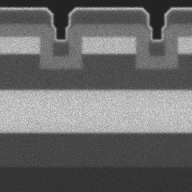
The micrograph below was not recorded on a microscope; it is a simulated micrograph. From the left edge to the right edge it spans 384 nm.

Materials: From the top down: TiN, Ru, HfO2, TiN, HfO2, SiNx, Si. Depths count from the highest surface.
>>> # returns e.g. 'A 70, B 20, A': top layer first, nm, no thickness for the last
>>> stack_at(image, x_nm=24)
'TiN 32, Ru 26, HfO2 34, TiN 72, HfO2 86, SiNx 68, Si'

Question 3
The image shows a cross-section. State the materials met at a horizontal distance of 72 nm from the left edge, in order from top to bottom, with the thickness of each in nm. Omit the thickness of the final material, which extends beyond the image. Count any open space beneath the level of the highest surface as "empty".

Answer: TiN 32, Ru 26, HfO2 34, TiN 72, HfO2 86, SiNx 68, Si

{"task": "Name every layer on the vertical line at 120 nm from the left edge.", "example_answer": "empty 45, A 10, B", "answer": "empty 64, TiN 32, Ru 26, TiN 42, HfO2 86, SiNx 68, Si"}